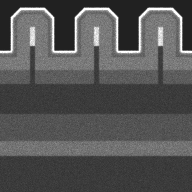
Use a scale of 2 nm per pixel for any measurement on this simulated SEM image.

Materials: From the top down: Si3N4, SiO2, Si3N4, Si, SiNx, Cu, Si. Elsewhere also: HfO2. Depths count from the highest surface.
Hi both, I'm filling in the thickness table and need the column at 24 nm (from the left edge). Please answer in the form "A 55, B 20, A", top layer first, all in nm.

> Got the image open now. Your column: empty 16, Si3N4 82, SiO2 26, Si3N4 28, Si 60, SiNx 54, Cu 30, Si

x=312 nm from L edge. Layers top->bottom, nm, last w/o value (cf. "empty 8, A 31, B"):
Si3N4 12, SiO2 112, Si3N4 28, Si 60, SiNx 54, Cu 30, Si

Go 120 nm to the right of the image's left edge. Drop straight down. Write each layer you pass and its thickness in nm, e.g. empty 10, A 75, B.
empty 86, Si3N4 12, SiO2 26, Si3N4 28, Si 60, SiNx 54, Cu 30, Si